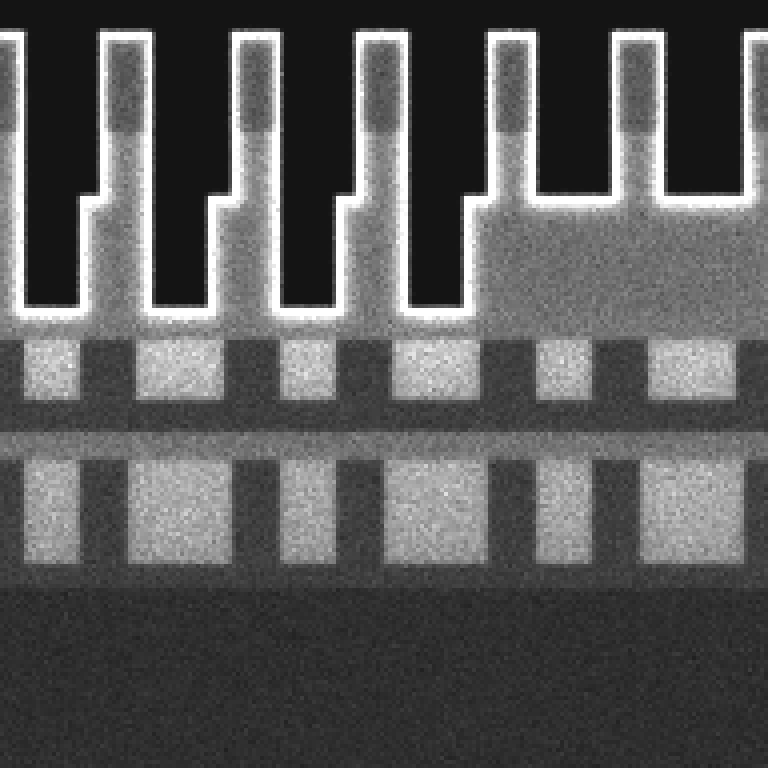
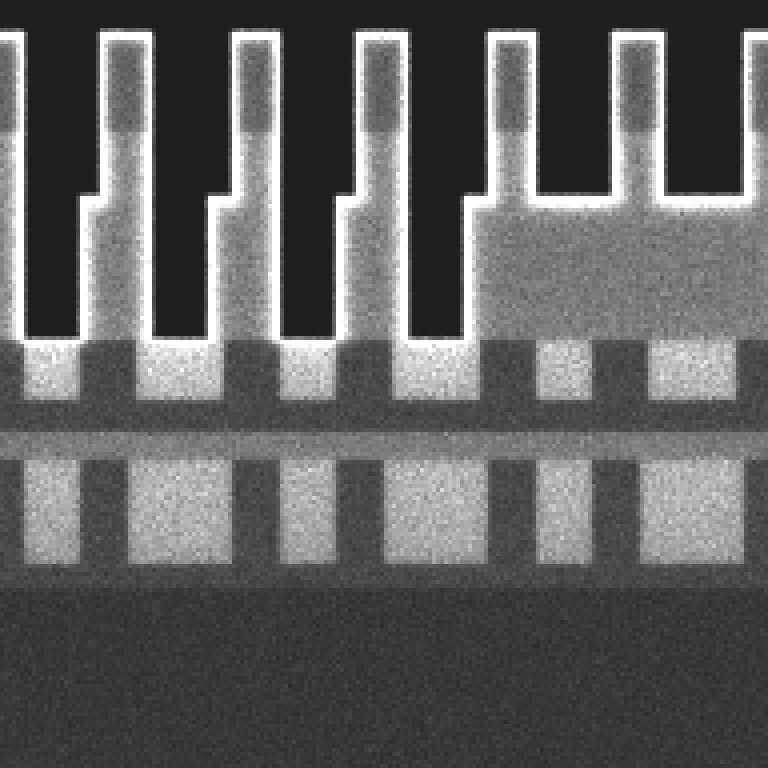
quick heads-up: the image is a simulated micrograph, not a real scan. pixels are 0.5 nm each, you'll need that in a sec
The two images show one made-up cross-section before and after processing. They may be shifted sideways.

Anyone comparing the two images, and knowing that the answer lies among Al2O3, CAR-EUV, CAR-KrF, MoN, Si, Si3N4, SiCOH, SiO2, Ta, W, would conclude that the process removed Al2O3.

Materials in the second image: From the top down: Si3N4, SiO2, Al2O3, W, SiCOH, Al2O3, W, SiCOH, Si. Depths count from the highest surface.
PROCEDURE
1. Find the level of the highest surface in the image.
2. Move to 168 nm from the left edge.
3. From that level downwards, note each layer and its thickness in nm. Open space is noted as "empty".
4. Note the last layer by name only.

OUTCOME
empty 82, SiO2 56, Al2O3 16, SiCOH 46, Al2O3 14, SiCOH 64, Si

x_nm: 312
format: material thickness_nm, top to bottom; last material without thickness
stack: Si3N4 50, SiO2 88, Al2O3 16, SiCOH 46, Al2O3 14, SiCOH 64, Si